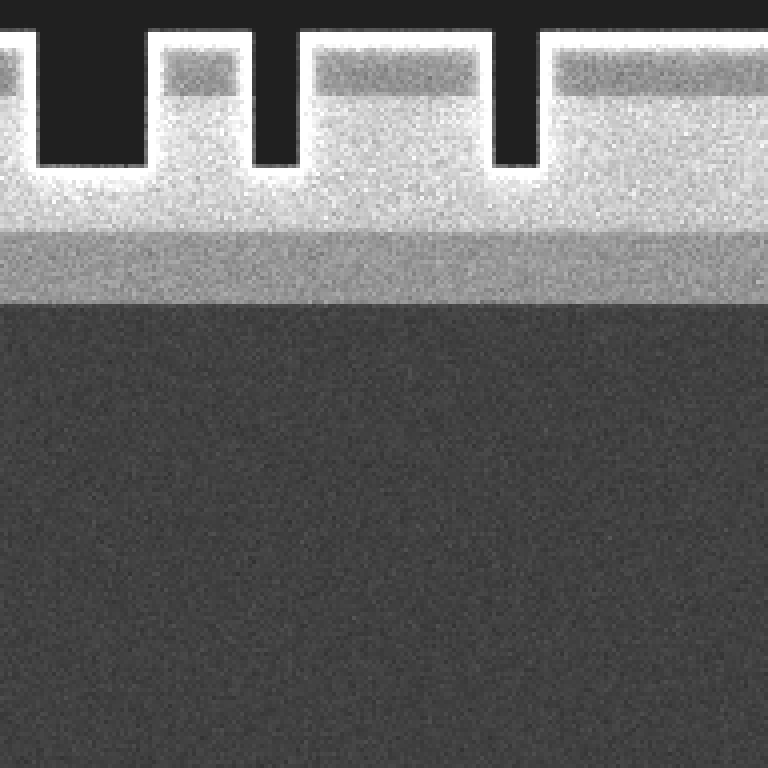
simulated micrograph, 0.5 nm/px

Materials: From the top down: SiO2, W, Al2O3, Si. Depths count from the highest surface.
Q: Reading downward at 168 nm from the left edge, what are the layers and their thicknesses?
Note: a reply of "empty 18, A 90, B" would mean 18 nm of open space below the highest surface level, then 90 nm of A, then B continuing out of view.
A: SiO2 32, W 68, Al2O3 36, Si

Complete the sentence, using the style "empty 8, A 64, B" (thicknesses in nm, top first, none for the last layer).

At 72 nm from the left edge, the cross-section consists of empty 68, W 32, Al2O3 36, Si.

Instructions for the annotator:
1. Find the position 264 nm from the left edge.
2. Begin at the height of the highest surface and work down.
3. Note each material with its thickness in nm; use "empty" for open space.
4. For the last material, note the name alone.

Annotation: empty 68, W 32, Al2O3 36, Si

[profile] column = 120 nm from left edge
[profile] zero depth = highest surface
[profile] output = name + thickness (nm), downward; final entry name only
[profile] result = SiO2 32, W 68, Al2O3 36, Si